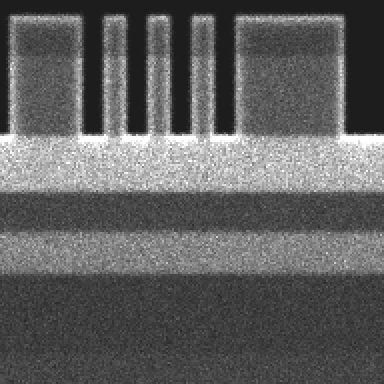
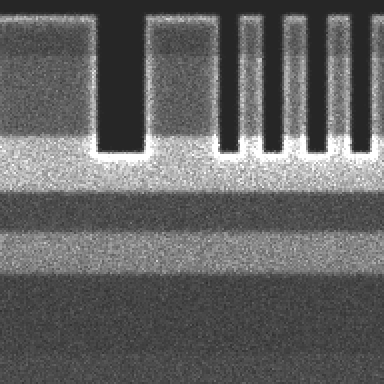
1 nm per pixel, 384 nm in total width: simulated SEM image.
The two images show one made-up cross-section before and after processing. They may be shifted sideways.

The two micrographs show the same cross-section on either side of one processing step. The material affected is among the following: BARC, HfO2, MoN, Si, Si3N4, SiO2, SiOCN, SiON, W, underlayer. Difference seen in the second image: HfO2 removed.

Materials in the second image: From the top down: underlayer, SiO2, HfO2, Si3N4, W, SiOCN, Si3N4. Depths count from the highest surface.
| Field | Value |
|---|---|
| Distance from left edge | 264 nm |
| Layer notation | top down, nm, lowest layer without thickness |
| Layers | empty 138, HfO2 38, Si3N4 40, W 42, SiOCN 80, Si3N4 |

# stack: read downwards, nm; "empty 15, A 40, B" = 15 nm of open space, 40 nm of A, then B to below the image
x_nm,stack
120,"empty 138, HfO2 38, Si3N4 40, W 42, SiOCN 80, Si3N4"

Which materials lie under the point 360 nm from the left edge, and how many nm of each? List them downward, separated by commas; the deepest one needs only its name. empty 138, HfO2 38, Si3N4 40, W 42, SiOCN 80, Si3N4